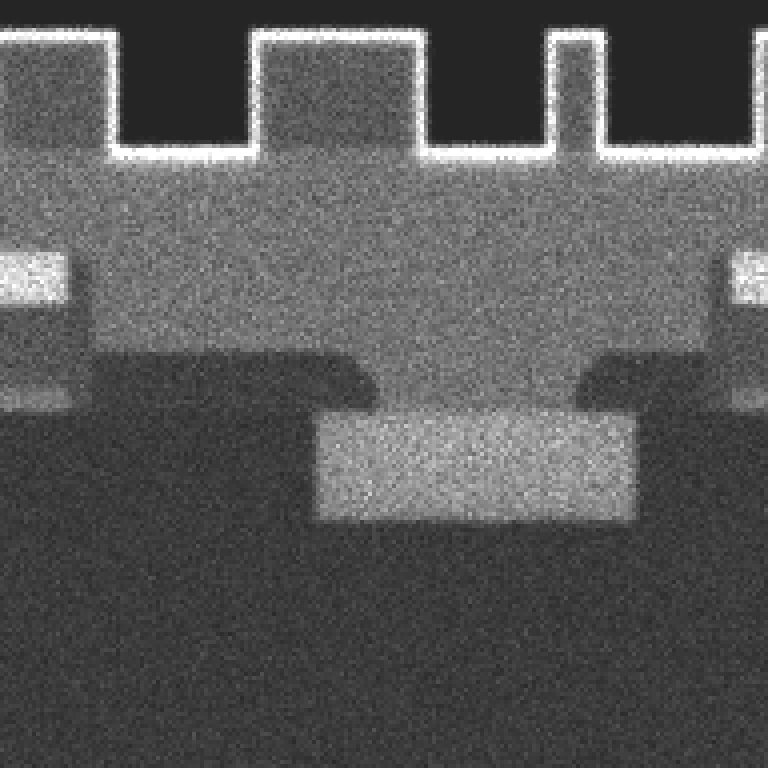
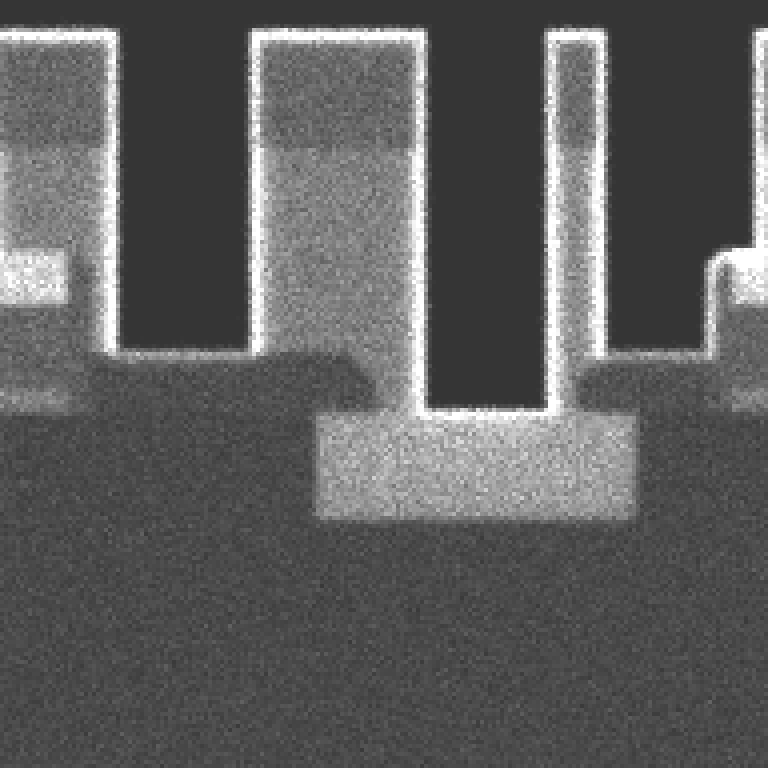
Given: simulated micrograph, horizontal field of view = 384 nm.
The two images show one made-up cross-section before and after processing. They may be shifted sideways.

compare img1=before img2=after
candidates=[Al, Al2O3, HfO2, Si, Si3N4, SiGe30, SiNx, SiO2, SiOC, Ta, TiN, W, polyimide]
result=removed:SiO2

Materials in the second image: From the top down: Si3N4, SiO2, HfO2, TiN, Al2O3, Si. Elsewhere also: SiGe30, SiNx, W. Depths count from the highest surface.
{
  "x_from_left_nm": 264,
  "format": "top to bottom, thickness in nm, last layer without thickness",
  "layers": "empty 190, W 54, Si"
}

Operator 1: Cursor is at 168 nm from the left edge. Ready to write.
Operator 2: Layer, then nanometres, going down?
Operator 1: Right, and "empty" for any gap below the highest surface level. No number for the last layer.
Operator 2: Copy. Si3N4 58, SiO2 102, SiGe30 30, W 54, Si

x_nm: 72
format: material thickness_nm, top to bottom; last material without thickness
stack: empty 160, SiGe30 30, Si